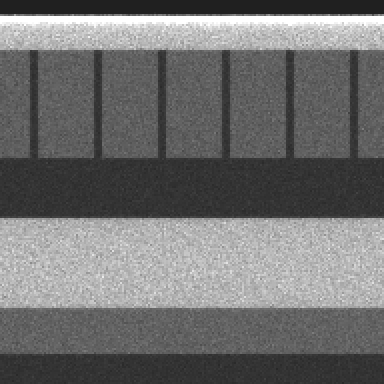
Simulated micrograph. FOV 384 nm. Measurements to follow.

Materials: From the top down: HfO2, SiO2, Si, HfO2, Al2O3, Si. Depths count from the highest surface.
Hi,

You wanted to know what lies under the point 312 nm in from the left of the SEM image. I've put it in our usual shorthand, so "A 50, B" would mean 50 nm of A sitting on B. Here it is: HfO2 34, SiO2 108, Si 60, HfO2 90, Al2O3 46, Si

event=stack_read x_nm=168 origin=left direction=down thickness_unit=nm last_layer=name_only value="HfO2 34, SiO2 108, Si 60, HfO2 90, Al2O3 46, Si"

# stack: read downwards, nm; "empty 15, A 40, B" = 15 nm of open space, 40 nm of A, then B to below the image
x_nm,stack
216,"HfO2 34, SiO2 108, Si 60, HfO2 90, Al2O3 46, Si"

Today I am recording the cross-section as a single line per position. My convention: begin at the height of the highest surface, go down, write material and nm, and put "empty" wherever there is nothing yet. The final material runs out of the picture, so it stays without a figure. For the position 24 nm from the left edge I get HfO2 34, SiO2 108, Si 60, HfO2 90, Al2O3 46, Si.